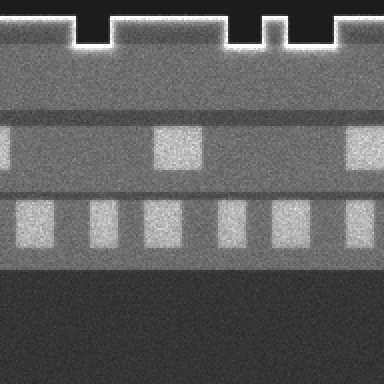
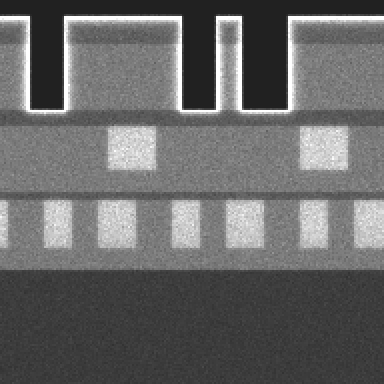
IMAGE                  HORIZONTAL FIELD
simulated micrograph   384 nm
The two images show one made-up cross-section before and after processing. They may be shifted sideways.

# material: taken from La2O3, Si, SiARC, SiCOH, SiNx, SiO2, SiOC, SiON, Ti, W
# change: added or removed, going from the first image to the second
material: SiO2
change: removed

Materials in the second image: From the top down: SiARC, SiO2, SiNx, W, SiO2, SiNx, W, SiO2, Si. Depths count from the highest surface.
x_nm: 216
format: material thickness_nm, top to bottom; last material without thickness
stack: SiARC 28, SiO2 66, SiNx 16, SiO2 66, SiNx 8, SiO2 70, Si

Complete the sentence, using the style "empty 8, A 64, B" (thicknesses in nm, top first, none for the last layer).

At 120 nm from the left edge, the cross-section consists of SiARC 28, SiO2 66, SiNx 16, W 44, SiO2 22, SiNx 8, W 48, SiO2 22, Si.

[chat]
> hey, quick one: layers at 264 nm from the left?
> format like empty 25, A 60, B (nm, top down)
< empty 94, SiNx 16, SiO2 66, SiNx 8, SiO2 70, Si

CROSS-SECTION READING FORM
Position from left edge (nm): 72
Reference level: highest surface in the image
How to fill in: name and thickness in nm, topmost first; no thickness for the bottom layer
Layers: SiARC 28, SiO2 66, SiNx 16, SiO2 66, SiNx 8, SiO2 70, Si